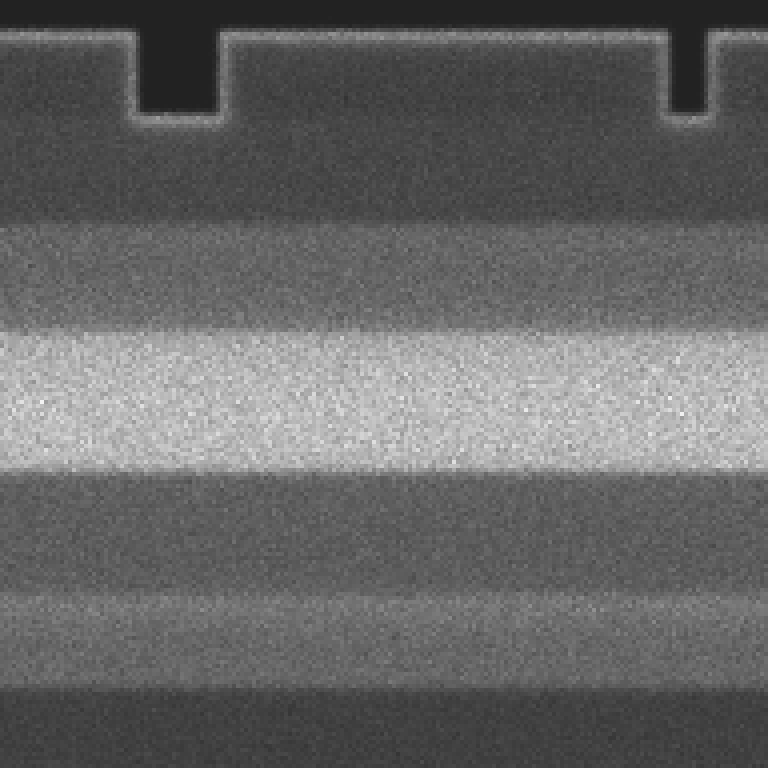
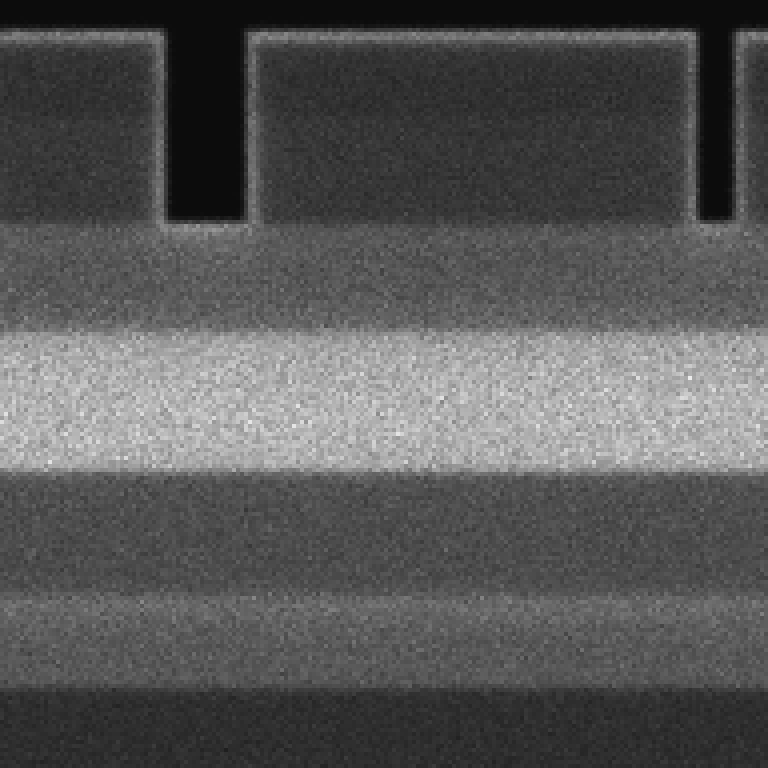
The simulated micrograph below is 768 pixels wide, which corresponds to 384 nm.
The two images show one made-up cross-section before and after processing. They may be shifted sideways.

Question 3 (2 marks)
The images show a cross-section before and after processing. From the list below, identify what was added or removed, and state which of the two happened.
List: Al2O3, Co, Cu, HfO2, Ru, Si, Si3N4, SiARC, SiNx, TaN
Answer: Si3N4 was removed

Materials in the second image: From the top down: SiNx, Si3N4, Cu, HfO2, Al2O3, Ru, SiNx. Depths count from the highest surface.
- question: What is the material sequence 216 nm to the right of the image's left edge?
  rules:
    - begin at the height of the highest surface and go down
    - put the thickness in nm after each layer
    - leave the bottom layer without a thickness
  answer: SiNx 42, Si3N4 54, Cu 54, HfO2 70, Al2O3 62, Ru 46, SiNx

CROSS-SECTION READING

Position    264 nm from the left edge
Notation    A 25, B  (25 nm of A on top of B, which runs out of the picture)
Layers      SiNx 42, Si3N4 54, Cu 54, HfO2 70, Al2O3 62, Ru 46, SiNx